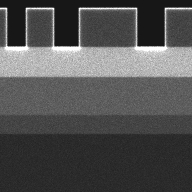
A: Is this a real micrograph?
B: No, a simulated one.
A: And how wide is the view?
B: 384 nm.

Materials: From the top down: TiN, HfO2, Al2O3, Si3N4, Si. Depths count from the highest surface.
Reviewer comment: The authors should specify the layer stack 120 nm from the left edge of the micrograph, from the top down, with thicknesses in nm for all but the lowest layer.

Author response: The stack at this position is empty 78, HfO2 60, Al2O3 76, Si3N4 38, Si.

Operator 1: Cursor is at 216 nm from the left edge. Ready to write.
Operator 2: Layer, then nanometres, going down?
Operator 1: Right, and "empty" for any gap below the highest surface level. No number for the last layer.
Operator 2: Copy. TiN 78, HfO2 60, Al2O3 76, Si3N4 38, Si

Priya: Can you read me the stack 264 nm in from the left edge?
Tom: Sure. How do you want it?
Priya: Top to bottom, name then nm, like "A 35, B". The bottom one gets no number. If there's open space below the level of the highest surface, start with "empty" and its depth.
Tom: TiN 78, HfO2 60, Al2O3 76, Si3N4 38, Si